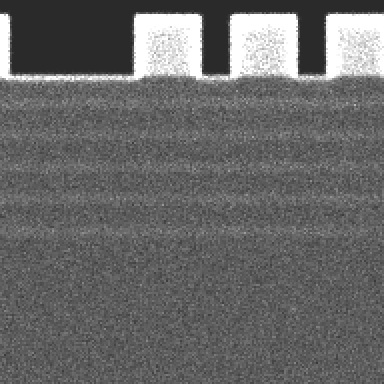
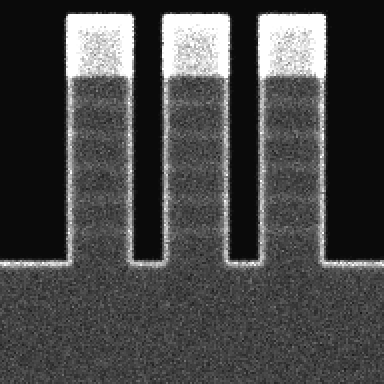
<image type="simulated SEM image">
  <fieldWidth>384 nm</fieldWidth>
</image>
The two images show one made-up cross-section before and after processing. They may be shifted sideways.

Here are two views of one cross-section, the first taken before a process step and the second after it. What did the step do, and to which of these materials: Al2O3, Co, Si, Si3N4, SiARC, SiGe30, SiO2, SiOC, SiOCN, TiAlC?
It removed Si and SiGe30.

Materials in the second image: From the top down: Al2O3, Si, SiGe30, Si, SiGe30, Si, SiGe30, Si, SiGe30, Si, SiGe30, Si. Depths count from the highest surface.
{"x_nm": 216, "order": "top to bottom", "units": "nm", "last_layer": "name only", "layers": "Al2O3 60, Si 22, SiGe30 10, Si 22, SiGe30 10, Si 22, SiGe30 10, Si 22, SiGe30 10, Si 22, SiGe30 10, Si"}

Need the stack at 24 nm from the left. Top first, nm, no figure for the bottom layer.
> empty 246, Si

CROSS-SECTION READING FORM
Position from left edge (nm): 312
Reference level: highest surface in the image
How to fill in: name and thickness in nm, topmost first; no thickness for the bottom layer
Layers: Al2O3 60, Si 22, SiGe30 10, Si 22, SiGe30 10, Si 22, SiGe30 10, Si 22, SiGe30 10, Si 22, SiGe30 10, Si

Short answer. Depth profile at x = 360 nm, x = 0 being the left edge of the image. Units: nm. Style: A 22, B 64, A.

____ empty 246, Si